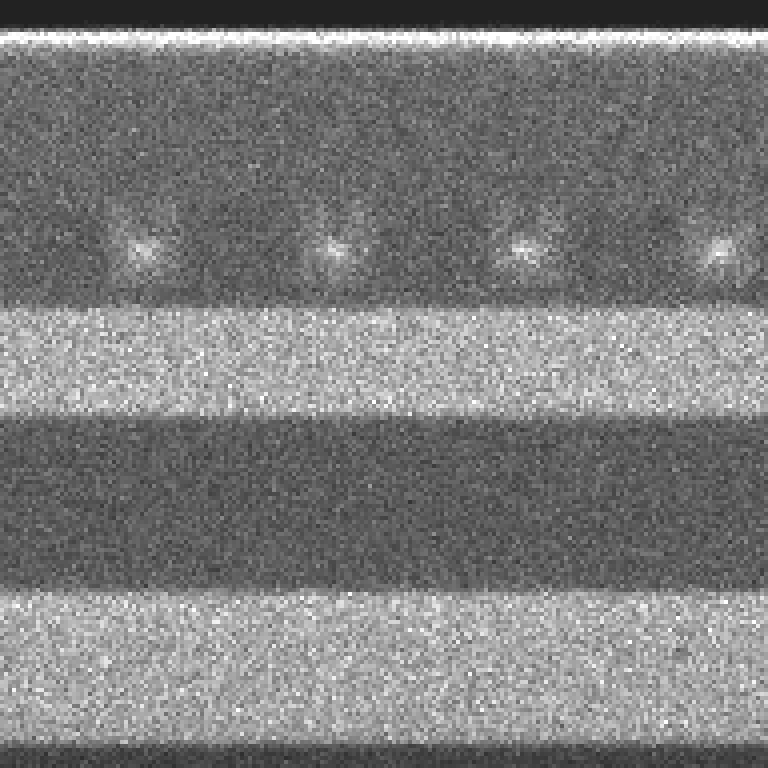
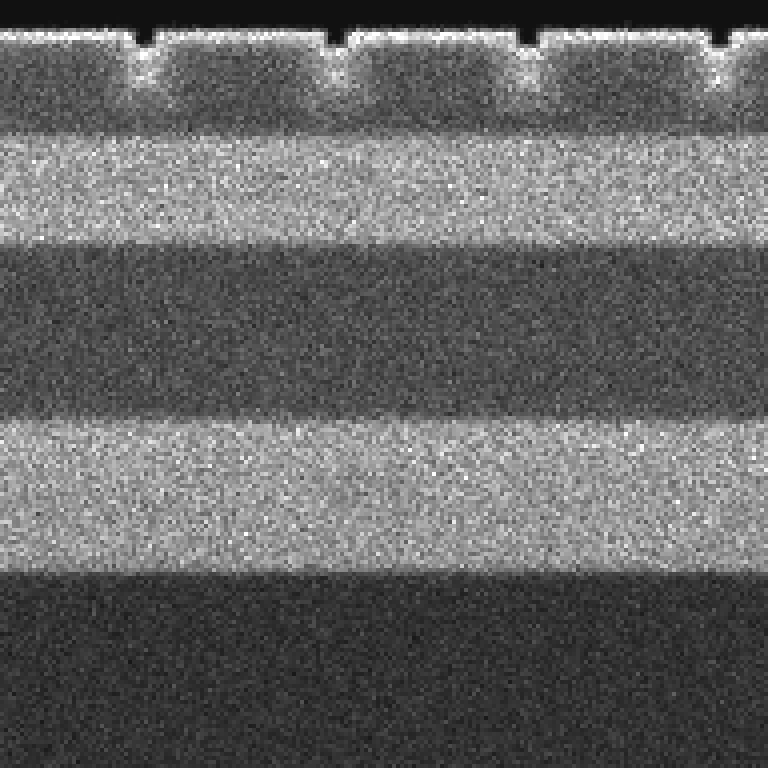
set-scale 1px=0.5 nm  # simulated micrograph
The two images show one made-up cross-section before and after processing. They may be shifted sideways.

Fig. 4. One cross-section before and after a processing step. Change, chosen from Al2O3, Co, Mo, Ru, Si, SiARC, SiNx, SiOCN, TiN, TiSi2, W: SiARC removed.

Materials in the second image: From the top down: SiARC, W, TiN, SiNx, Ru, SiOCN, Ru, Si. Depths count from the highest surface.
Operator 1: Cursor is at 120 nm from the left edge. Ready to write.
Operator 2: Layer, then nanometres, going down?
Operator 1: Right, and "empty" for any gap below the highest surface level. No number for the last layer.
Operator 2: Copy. SiNx 52, Ru 54, SiOCN 88, Ru 76, Si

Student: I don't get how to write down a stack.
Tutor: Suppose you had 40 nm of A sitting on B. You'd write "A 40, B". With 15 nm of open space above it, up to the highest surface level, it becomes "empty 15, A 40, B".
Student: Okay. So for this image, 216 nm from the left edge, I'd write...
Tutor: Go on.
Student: SiNx 52, Ru 54, SiOCN 88, Ru 76, Si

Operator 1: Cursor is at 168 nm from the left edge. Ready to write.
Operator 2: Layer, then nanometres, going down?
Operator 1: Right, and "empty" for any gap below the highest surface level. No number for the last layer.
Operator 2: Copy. empty 8, SiARC 10, W 10, TiN 12, SiNx 12, Ru 54, SiOCN 88, Ru 76, Si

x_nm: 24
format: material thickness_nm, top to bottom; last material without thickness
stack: SiNx 52, Ru 54, SiOCN 88, Ru 76, Si